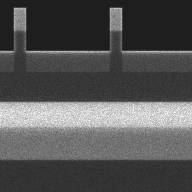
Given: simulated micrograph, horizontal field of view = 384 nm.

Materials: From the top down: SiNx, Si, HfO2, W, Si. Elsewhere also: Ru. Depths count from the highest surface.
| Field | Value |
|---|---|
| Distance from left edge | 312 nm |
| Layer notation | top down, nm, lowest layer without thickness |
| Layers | empty 86, SiNx 42, Si 60, HfO2 50, W 66, Si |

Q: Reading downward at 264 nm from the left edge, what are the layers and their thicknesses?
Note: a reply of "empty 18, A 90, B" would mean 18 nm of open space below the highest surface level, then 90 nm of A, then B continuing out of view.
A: empty 86, SiNx 42, Si 60, HfO2 50, W 66, Si